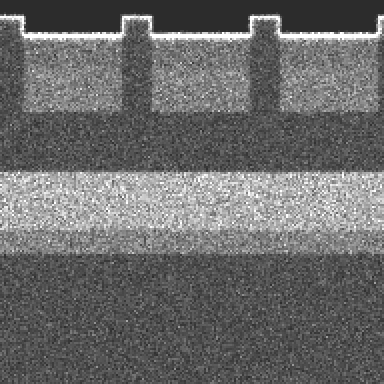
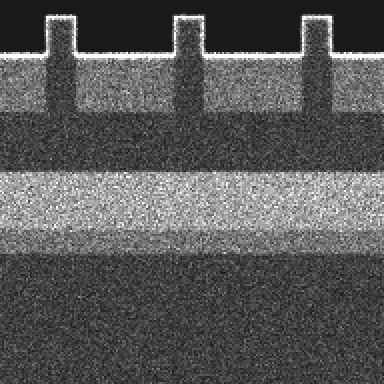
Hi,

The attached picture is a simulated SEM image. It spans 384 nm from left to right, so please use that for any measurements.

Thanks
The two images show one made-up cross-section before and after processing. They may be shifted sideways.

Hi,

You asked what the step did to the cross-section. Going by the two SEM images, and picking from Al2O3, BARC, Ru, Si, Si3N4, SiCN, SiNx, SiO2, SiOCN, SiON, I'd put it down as SiNx, removed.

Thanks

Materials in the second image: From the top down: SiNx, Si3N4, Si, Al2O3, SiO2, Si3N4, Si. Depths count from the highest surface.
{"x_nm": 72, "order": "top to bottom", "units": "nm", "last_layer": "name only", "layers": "Si 156, Al2O3 26, SiO2 32, Si3N4 24, Si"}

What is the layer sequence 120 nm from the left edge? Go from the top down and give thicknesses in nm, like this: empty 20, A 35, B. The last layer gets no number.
empty 38, SiNx 14, Si3N4 44, Si 60, Al2O3 26, SiO2 32, Si3N4 24, Si